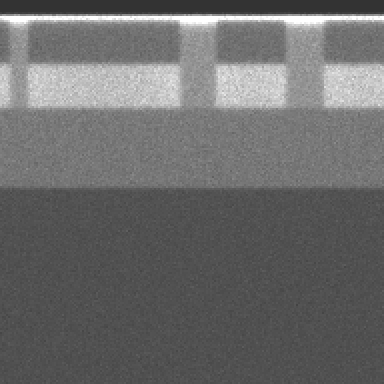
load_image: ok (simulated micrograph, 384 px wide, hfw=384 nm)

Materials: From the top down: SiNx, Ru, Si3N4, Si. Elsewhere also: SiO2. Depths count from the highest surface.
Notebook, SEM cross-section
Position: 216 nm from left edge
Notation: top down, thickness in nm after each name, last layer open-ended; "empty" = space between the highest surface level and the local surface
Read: SiNx 48, Ru 44, Si3N4 80, Si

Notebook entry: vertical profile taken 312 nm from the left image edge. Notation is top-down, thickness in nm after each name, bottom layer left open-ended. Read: SiO2 92, Si3N4 80, Si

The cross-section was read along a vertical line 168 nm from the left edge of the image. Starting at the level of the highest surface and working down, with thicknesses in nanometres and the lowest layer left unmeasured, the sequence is SiNx 48, Ru 44, Si3N4 80, Si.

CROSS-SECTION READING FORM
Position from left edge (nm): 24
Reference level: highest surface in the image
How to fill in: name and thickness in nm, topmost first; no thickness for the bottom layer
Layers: SiO2 92, Si3N4 80, Si